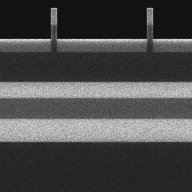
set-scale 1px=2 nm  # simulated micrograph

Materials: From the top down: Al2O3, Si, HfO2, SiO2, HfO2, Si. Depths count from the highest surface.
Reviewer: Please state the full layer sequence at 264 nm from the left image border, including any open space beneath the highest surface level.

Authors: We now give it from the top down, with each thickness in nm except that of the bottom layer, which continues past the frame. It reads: empty 62, Al2O3 26, Si 60, HfO2 32, SiO2 42, HfO2 46, Si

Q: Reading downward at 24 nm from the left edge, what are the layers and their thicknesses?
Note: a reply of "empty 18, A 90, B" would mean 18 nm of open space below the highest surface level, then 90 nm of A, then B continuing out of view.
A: empty 62, Al2O3 26, Si 60, HfO2 32, SiO2 42, HfO2 46, Si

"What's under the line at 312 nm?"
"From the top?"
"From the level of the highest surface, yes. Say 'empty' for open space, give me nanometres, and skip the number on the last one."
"empty 62, Al2O3 26, Si 60, HfO2 32, SiO2 42, HfO2 46, Si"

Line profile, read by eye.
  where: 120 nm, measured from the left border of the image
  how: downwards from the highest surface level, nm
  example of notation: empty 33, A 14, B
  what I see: empty 62, Al2O3 26, Si 60, HfO2 32, SiO2 42, HfO2 46, Si